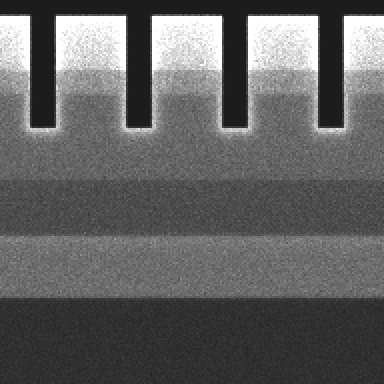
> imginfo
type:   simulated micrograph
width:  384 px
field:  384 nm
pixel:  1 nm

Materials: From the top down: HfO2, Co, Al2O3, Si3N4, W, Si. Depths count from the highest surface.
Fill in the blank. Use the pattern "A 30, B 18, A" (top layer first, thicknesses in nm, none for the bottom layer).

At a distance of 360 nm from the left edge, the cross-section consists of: HfO2 54, Co 24, Al2O3 86, Si3N4 56, W 62, Si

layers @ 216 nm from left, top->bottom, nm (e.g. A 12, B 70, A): HfO2 54, Co 24, Al2O3 86, Si3N4 56, W 62, Si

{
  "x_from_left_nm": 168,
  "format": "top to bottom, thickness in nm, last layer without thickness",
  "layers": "HfO2 54, Co 24, Al2O3 86, Si3N4 56, W 62, Si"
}